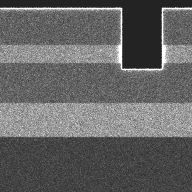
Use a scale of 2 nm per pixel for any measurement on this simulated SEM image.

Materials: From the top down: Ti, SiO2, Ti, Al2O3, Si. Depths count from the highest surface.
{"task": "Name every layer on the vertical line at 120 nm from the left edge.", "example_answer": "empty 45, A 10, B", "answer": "Ti 74, SiO2 36, Ti 80, Al2O3 68, Si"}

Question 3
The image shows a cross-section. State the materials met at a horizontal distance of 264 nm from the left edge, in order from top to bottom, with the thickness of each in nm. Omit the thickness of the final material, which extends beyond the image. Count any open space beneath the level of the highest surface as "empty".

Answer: empty 122, Ti 68, Al2O3 68, Si